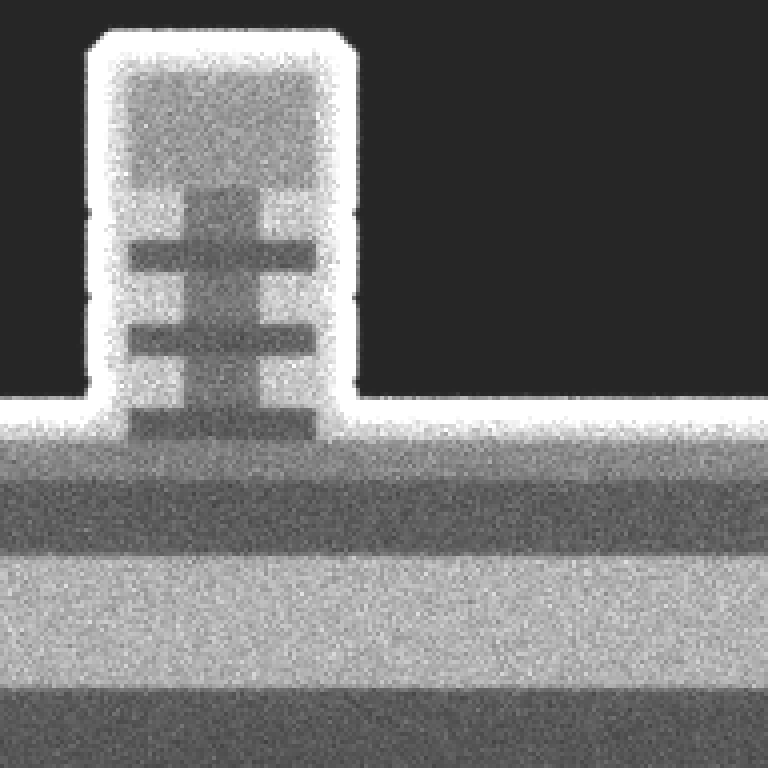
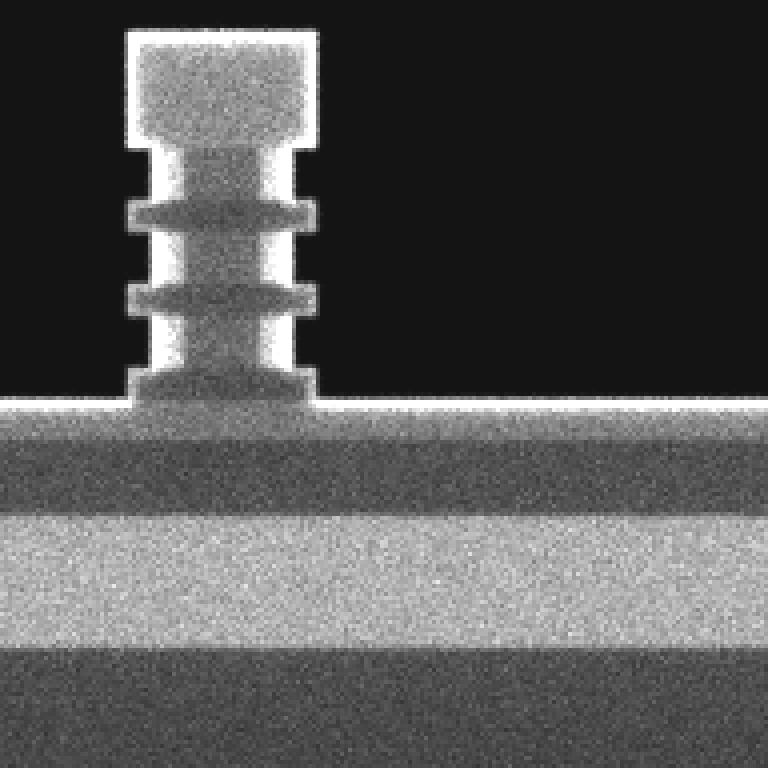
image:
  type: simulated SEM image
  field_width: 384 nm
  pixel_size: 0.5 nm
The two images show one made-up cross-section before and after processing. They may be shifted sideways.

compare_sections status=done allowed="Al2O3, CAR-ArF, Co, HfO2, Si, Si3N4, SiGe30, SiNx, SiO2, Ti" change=removed material="Al2O3"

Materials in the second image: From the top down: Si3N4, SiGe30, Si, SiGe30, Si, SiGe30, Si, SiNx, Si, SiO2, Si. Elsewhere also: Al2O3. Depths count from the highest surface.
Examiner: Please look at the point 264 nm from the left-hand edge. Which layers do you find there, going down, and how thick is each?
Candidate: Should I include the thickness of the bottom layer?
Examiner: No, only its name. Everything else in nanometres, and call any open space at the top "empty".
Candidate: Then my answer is empty 184, SiNx 20, Si 38, SiO2 66, Si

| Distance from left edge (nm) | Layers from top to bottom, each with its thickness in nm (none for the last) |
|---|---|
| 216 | empty 184, SiNx 20, Si 38, SiO2 66, Si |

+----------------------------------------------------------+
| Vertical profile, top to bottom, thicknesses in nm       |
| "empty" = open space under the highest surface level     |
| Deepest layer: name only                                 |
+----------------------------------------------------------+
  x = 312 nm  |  empty 184, SiNx 20, Si 38, SiO2 66, Si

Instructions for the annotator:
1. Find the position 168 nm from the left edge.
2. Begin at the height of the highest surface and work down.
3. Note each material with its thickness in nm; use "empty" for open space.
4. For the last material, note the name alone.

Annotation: empty 184, SiNx 20, Si 38, SiO2 66, Si